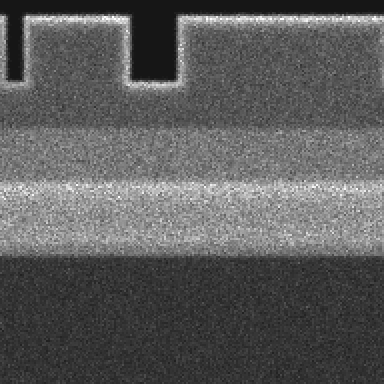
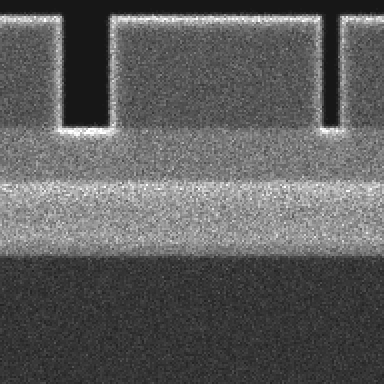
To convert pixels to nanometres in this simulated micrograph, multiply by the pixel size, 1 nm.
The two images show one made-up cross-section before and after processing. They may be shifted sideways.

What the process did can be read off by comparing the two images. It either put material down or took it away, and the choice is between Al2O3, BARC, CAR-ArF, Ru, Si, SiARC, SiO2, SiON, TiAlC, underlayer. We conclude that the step removed underlayer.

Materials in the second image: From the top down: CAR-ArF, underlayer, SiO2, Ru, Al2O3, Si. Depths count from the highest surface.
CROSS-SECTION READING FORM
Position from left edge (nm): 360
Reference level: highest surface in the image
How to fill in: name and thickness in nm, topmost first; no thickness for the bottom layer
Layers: CAR-ArF 66, underlayer 46, SiO2 54, Ru 62, Al2O3 12, Si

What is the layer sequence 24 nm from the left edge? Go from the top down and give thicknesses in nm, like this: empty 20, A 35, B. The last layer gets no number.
CAR-ArF 66, underlayer 46, SiO2 54, Ru 62, Al2O3 12, Si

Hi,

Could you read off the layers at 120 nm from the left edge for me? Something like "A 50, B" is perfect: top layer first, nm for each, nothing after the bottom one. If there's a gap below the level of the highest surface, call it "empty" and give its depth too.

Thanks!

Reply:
CAR-ArF 66, underlayer 46, SiO2 54, Ru 62, Al2O3 12, Si